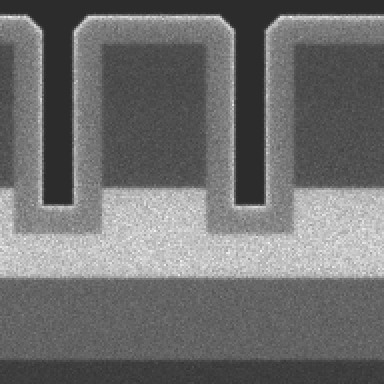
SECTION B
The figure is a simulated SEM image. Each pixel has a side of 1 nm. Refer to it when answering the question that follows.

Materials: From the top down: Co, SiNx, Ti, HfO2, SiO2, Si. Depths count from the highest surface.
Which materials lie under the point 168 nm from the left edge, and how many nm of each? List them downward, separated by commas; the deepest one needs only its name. Co 28, SiNx 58, Ti 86, HfO2 90, SiO2 82, Si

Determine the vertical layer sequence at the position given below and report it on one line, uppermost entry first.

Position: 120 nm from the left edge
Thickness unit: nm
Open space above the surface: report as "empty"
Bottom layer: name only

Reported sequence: Co 28, SiNx 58, Ti 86, HfO2 90, SiO2 82, Si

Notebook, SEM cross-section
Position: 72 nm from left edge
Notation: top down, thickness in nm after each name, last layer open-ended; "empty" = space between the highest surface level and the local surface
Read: empty 190, Co 28, HfO2 44, SiO2 82, Si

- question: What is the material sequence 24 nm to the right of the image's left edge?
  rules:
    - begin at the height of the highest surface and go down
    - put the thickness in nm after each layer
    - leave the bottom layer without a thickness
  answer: Co 218, HfO2 44, SiO2 82, Si